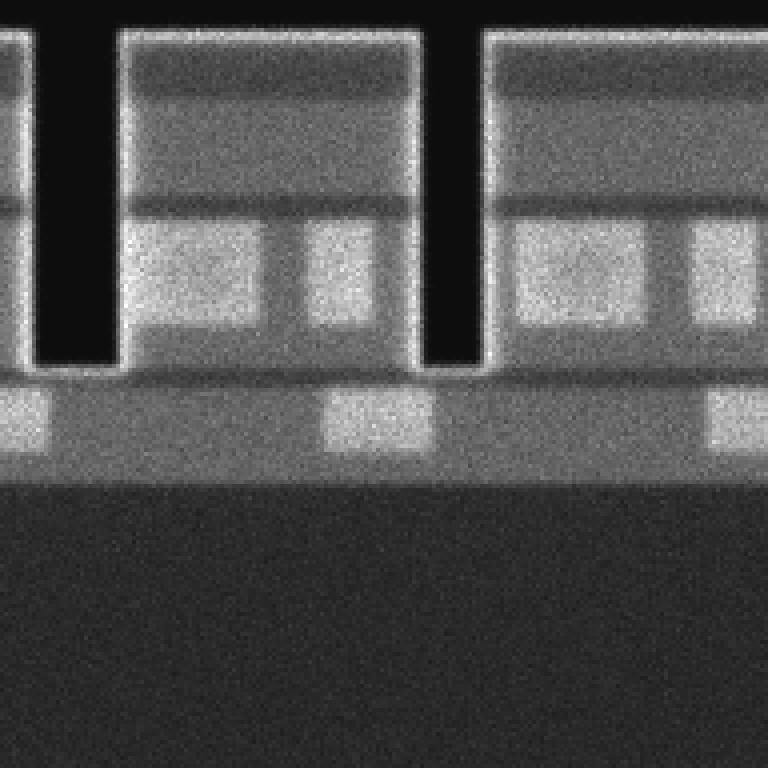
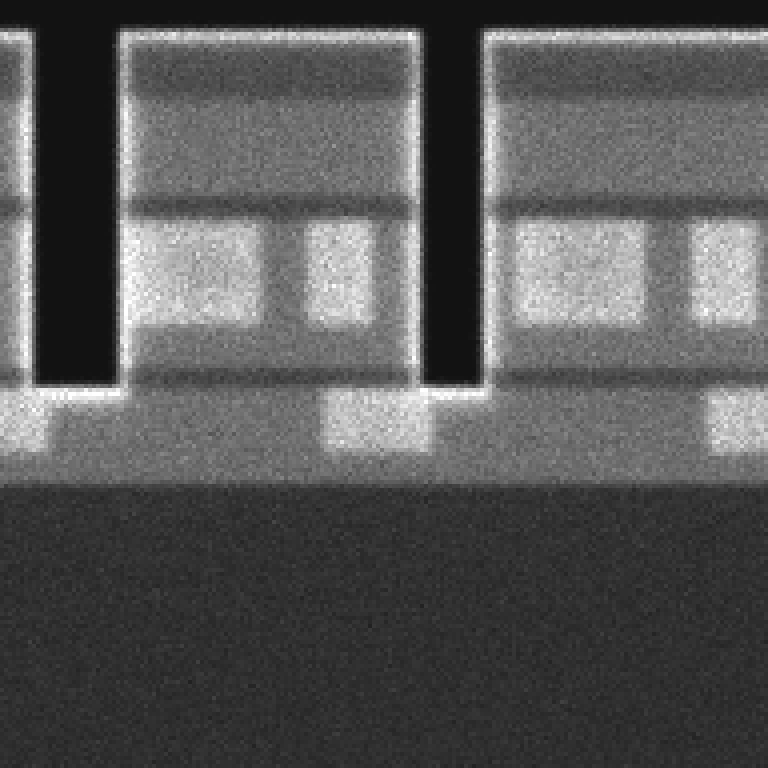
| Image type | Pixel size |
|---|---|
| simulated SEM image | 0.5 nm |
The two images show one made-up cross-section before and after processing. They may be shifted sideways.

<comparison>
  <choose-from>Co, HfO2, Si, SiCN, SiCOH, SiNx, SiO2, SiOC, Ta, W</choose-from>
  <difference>SiCN removed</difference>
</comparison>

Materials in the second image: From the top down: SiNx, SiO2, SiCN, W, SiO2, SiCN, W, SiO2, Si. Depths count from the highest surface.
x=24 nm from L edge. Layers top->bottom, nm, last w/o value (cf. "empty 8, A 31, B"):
empty 178, SiO2 48, Si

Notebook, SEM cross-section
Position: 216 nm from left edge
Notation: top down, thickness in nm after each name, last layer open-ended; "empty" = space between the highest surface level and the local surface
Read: empty 178, SiO2 48, Si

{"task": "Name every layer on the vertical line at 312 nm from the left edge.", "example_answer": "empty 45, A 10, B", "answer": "SiNx 34, SiO2 48, SiCN 12, W 52, SiO2 22, SiCN 10, SiO2 48, Si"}